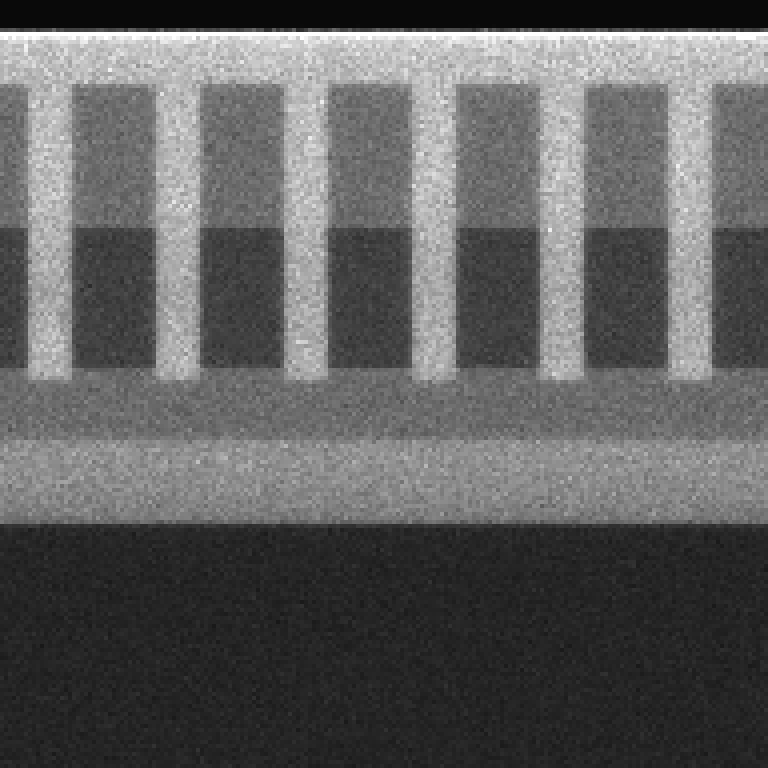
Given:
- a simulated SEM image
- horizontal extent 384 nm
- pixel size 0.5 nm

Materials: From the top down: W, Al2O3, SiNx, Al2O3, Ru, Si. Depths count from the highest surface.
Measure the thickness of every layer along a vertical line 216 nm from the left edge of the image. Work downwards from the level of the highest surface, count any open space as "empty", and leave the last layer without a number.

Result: W 174, Al2O3 30, Ru 42, Si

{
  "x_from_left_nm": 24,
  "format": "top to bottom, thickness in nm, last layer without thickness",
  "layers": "W 174, Al2O3 30, Ru 42, Si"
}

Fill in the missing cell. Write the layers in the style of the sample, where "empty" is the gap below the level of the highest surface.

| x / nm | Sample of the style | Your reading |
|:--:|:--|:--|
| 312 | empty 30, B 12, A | W 26, Al2O3 72, SiNx 70, Al2O3 36, Ru 42, Si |